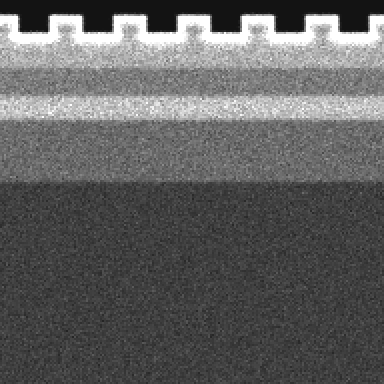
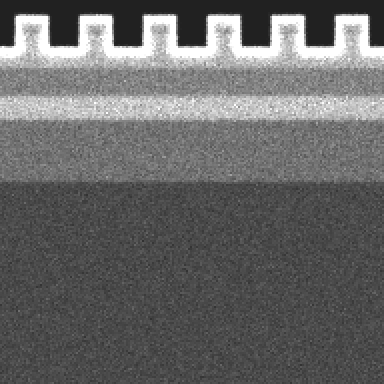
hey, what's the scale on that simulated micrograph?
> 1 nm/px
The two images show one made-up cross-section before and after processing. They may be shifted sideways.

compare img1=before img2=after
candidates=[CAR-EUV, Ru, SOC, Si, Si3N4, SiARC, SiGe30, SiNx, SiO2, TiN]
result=removed:SiO2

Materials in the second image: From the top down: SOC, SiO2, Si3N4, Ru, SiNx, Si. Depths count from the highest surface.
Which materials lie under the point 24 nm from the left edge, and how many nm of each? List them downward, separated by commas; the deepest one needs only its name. SOC 18, SiO2 34, Si3N4 28, Ru 24, SiNx 62, Si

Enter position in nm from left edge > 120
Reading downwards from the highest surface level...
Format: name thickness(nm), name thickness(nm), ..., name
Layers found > empty 32, SiO2 20, Si3N4 28, Ru 24, SiNx 62, Si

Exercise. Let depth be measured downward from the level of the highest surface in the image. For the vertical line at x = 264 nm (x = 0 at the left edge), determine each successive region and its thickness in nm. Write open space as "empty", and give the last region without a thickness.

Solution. empty 32, SiO2 20, Si3N4 28, Ru 24, SiNx 62, Si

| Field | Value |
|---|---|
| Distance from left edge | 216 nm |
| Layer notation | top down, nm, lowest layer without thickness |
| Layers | SOC 18, SiO2 34, Si3N4 28, Ru 24, SiNx 62, Si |